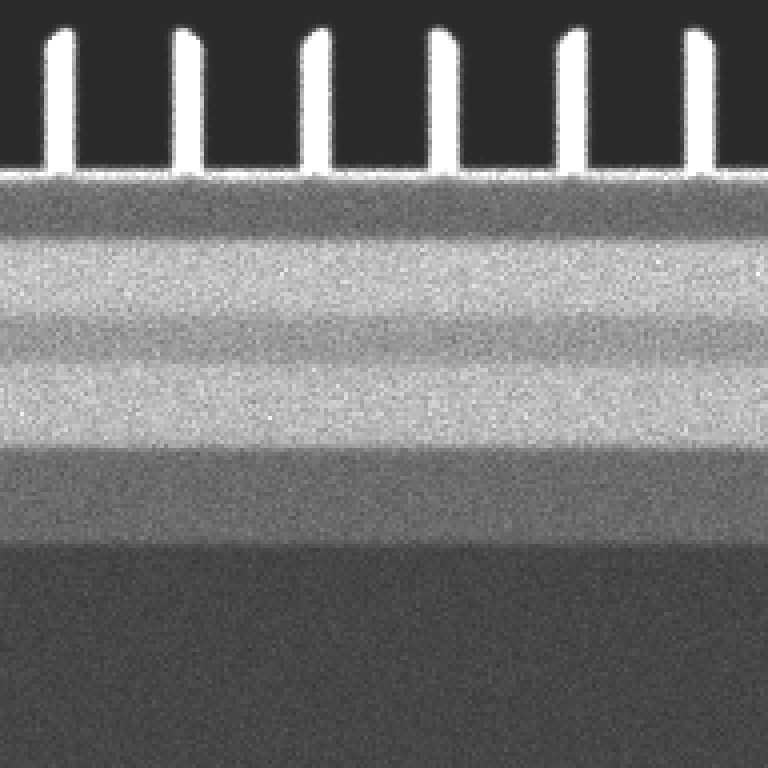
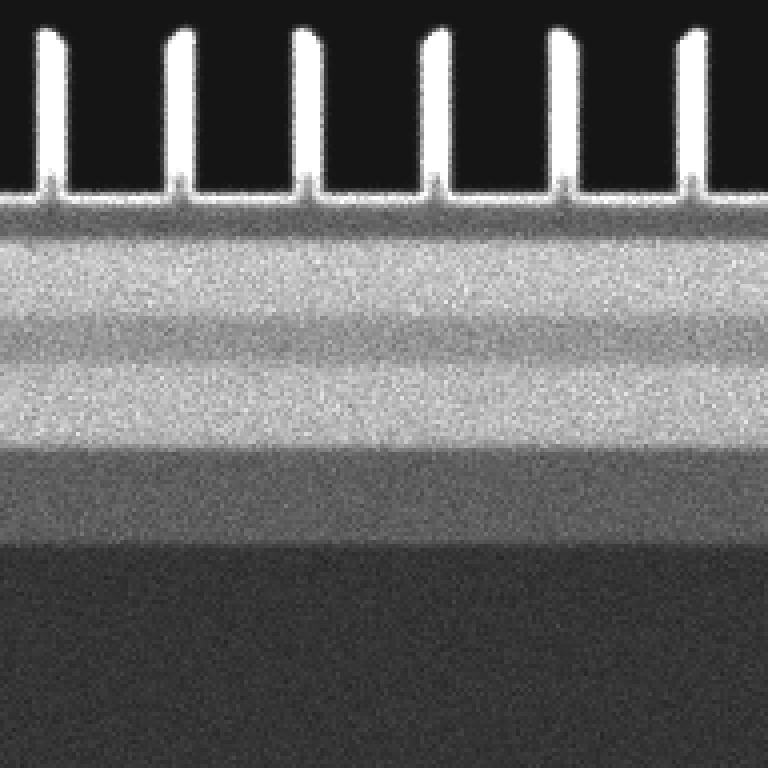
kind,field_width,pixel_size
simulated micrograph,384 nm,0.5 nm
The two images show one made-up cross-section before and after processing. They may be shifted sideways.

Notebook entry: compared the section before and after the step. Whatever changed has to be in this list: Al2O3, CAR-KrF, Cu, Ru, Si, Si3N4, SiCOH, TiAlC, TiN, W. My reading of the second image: TiN removed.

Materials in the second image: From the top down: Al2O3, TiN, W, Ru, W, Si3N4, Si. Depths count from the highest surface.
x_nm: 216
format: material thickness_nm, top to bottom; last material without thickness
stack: empty 2, Al2O3 68, TiN 34, W 38, Ru 24, W 42, Si3N4 48, Si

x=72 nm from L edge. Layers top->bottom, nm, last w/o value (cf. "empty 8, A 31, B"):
empty 82, TiN 22, W 38, Ru 24, W 42, Si3N4 48, Si